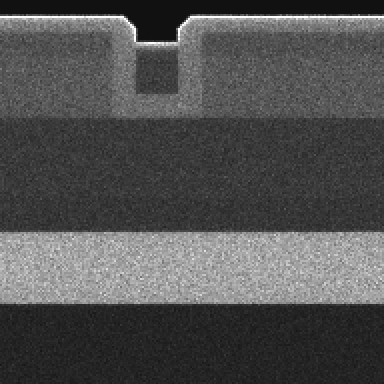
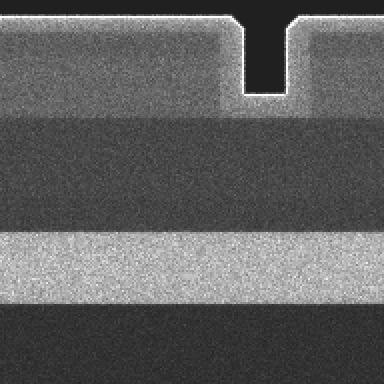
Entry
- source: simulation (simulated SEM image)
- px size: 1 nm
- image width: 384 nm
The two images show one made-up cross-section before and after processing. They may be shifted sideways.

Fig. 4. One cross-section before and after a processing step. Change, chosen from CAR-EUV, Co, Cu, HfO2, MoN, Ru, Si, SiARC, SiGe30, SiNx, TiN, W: SiARC removed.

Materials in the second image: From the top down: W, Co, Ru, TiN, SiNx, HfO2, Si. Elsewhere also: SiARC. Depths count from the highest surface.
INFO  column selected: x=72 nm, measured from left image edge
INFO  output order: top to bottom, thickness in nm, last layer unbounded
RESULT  W 16, Co 24, Ru 62, TiN 80, SiNx 34, HfO2 72, Si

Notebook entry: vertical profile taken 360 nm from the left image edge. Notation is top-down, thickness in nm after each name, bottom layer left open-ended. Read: W 16, Co 24, Ru 62, TiN 80, SiNx 34, HfO2 72, Si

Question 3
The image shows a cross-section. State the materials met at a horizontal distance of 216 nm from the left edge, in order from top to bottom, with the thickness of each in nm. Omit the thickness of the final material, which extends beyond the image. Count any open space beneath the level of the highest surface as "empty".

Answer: W 16, Co 24, Ru 62, TiN 80, SiNx 34, HfO2 72, Si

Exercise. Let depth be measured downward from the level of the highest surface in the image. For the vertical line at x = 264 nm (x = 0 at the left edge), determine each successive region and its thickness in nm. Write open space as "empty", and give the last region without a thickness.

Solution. empty 78, W 24, TiN 80, SiNx 34, HfO2 72, Si